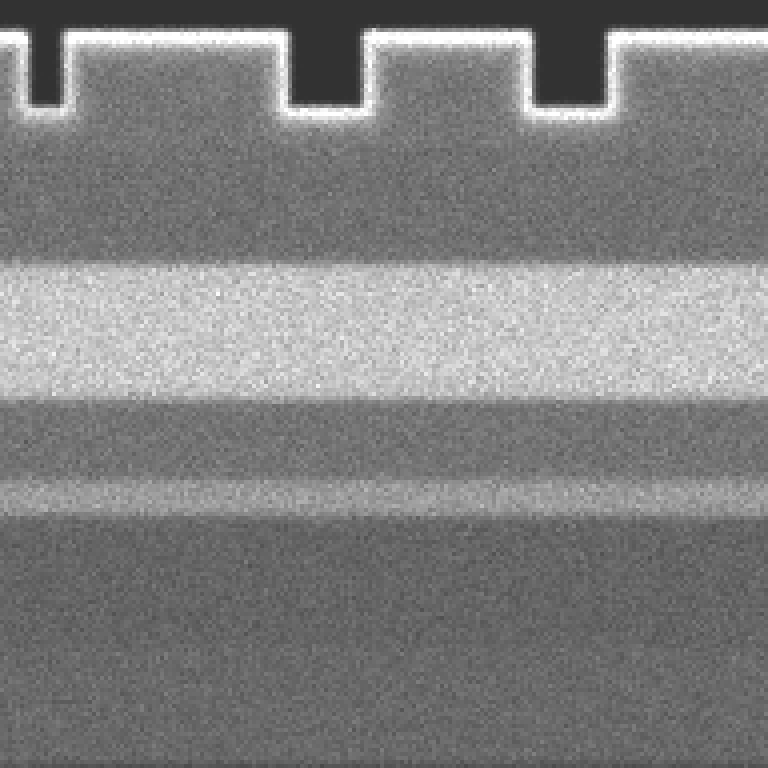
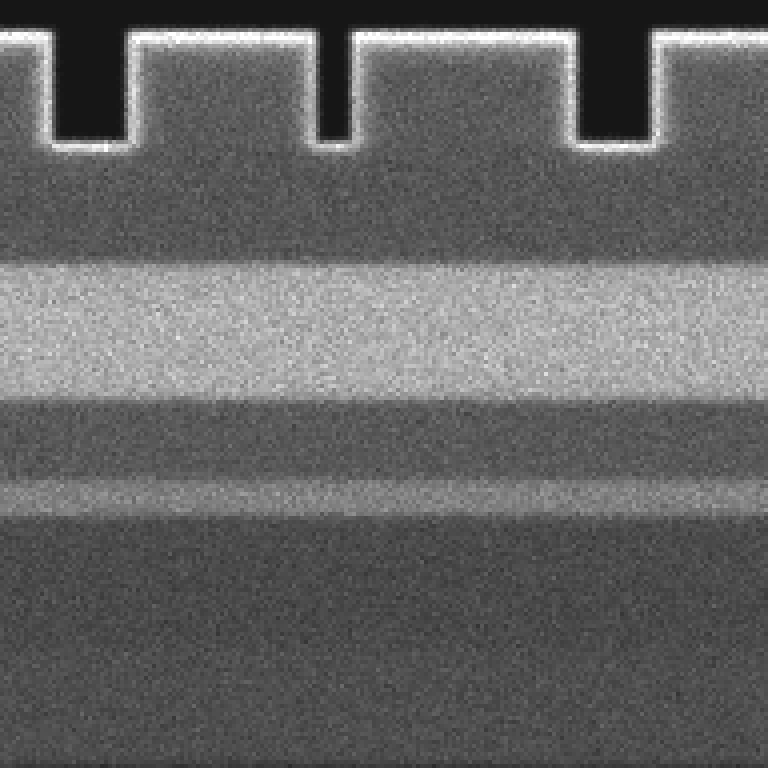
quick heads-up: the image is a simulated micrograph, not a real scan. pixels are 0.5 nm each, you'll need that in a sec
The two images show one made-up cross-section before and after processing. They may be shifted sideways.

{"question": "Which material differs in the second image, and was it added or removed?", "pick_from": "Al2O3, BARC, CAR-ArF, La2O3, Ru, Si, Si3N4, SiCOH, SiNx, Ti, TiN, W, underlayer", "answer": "underlayer, removed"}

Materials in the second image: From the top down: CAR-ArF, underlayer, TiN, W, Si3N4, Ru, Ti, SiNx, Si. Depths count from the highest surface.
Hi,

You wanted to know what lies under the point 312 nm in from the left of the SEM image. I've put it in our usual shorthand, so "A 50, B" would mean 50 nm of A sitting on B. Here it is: empty 56, TiN 60, W 68, Si3N4 40, Ru 18, Ti 66, SiNx 58, Si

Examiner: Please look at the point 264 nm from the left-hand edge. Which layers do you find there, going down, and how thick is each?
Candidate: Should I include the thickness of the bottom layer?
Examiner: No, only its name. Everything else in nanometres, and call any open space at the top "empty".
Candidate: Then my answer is CAR-ArF 38, underlayer 18, TiN 60, W 68, Si3N4 40, Ru 18, Ti 66, SiNx 58, Si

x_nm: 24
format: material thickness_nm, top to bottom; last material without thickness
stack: CAR-ArF 38, underlayer 18, TiN 60, W 68, Si3N4 40, Ru 18, Ti 66, SiNx 58, Si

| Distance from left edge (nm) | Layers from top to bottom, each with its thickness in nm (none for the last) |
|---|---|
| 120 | CAR-ArF 38, underlayer 18, TiN 60, W 68, Si3N4 40, Ru 18, Ti 66, SiNx 58, Si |